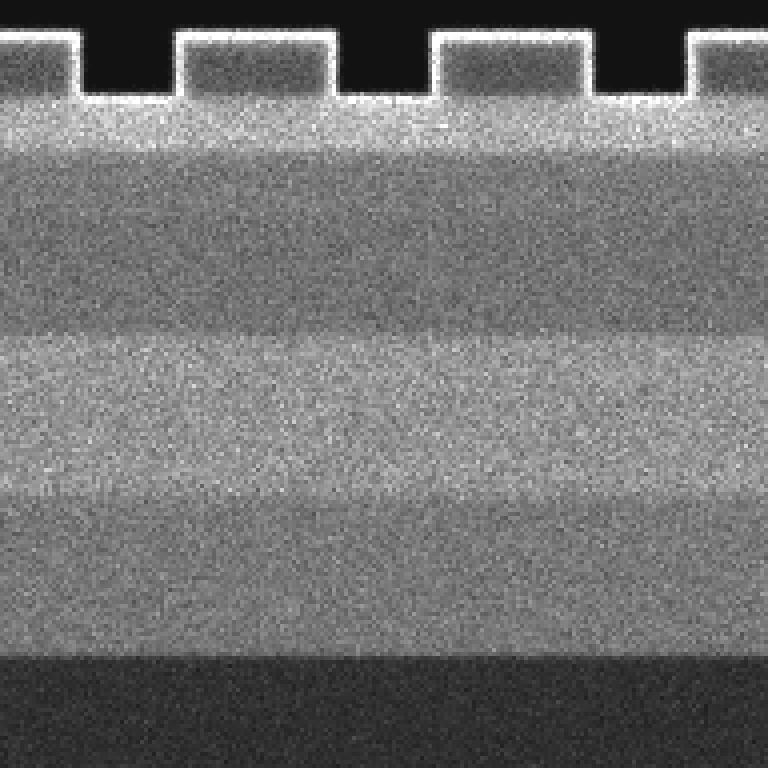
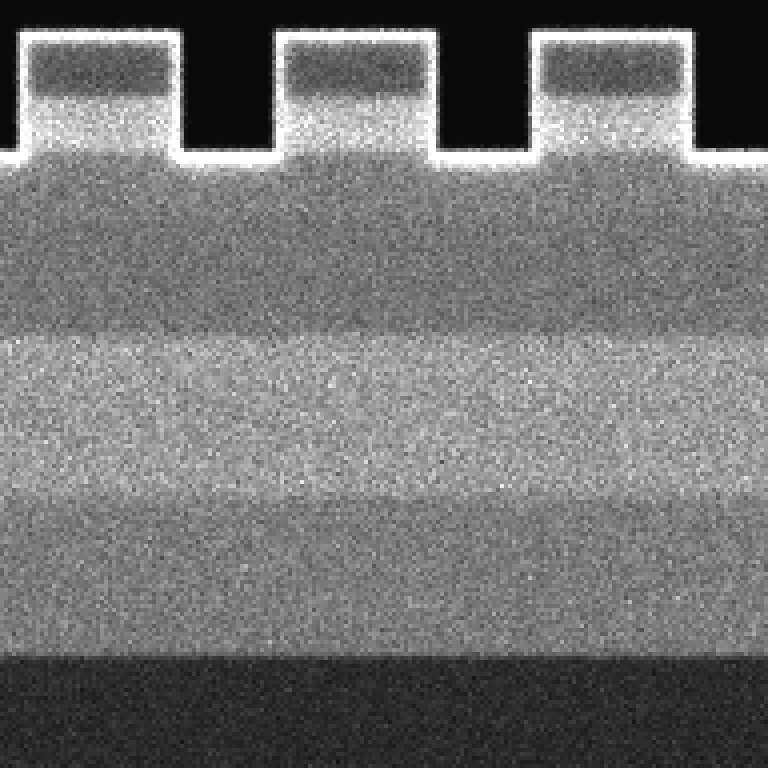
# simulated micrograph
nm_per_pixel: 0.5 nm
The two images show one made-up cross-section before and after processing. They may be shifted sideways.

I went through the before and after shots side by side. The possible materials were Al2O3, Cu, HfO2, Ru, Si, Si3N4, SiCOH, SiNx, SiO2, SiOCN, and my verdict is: removed, Ru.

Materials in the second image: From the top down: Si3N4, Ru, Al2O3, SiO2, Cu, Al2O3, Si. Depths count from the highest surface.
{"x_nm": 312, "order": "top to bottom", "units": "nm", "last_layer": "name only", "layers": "Si3N4 32, Ru 28, Al2O3 32, SiO2 60, Cu 80, Al2O3 80, Si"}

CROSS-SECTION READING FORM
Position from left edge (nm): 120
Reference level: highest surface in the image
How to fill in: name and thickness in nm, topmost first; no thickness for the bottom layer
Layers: empty 60, Al2O3 32, SiO2 60, Cu 80, Al2O3 80, Si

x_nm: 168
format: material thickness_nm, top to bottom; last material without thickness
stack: Si3N4 32, Ru 28, Al2O3 32, SiO2 60, Cu 80, Al2O3 80, Si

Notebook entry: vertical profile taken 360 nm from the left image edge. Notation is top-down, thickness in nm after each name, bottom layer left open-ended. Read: empty 60, Al2O3 32, SiO2 60, Cu 80, Al2O3 80, Si